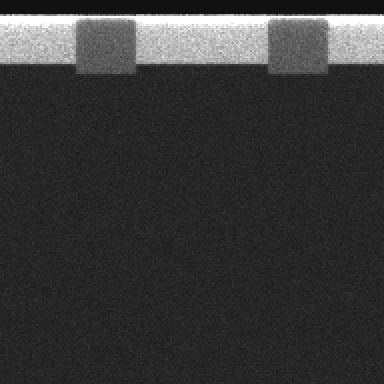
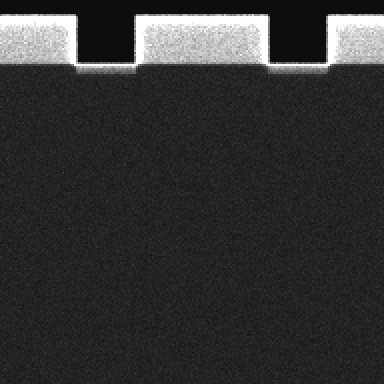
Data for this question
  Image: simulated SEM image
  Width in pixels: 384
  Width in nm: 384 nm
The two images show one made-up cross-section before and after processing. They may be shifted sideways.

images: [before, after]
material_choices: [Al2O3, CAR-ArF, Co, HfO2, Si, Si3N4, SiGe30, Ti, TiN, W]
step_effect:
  removed: Co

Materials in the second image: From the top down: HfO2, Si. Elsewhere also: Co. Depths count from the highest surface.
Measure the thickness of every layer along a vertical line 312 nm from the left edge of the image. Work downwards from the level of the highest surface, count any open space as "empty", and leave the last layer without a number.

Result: empty 48, Co 10, Si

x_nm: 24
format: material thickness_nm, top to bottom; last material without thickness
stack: HfO2 48, Si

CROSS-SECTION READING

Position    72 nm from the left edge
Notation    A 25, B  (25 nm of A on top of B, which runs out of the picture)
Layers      HfO2 48, Si